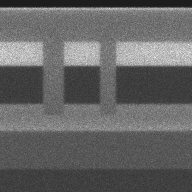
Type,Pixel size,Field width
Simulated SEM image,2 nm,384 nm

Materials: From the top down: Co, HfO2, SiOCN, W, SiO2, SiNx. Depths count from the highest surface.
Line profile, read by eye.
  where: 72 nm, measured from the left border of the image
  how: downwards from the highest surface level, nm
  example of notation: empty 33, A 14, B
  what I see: Co 68, HfO2 48, SiOCN 76, W 54, SiO2 76, SiNx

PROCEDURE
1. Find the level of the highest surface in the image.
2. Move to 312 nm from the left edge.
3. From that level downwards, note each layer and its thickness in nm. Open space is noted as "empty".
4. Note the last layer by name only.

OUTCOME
Co 68, HfO2 48, SiOCN 76, W 54, SiO2 76, SiNx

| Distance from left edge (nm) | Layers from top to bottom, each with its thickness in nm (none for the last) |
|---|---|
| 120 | Co 214, W 32, SiO2 76, SiNx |